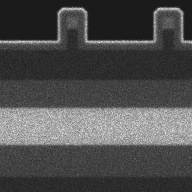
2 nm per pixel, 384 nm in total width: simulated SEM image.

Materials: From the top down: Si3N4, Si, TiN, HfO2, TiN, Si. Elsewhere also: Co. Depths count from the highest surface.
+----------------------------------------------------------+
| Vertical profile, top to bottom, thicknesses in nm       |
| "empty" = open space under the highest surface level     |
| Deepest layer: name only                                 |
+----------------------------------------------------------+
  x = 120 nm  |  empty 4, Si3N4 80, Si 60, TiN 56, HfO2 74, TiN 64, Si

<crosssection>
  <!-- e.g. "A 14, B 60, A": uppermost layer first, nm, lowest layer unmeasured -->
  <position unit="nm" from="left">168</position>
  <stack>empty 4, Si3N4 80, Si 60, TiN 56, HfO2 74, TiN 64, Si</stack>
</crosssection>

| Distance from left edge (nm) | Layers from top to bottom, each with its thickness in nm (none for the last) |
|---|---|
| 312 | empty 4, Si3N4 80, Si 60, TiN 56, HfO2 74, TiN 64, Si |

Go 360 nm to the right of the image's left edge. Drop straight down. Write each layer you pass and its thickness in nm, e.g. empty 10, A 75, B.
empty 4, Si3N4 80, Si 60, TiN 56, HfO2 74, TiN 64, Si